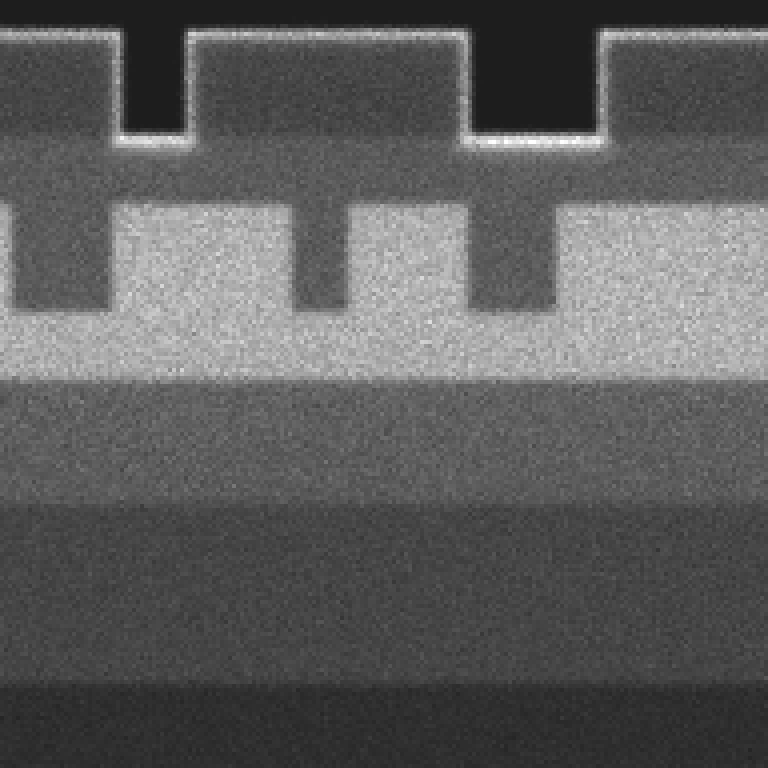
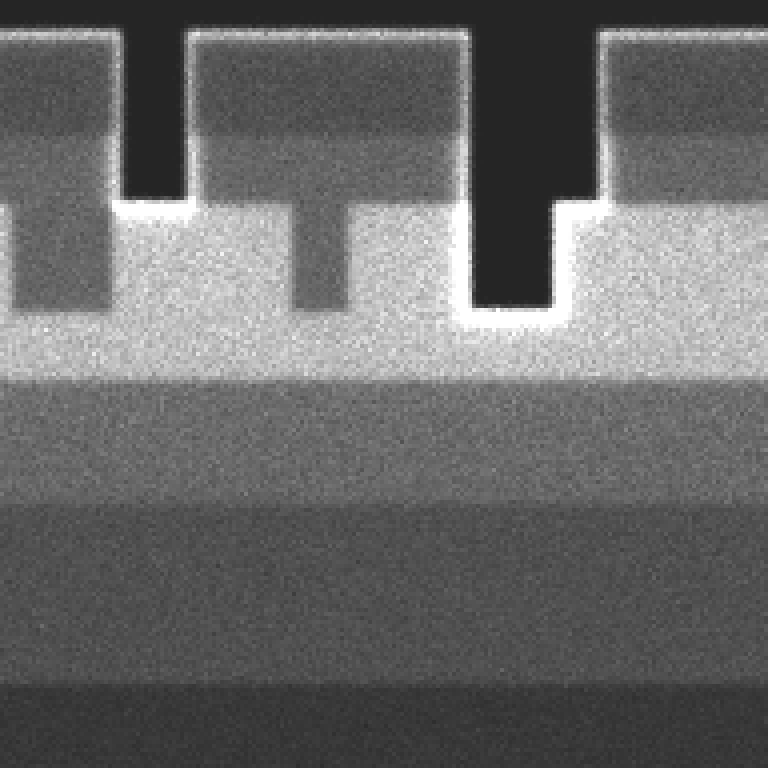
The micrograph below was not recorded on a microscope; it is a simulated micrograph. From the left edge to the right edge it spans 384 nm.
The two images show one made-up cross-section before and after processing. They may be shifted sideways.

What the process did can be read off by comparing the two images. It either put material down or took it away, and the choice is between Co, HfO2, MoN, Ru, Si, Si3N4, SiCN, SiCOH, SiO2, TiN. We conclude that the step removed SiO2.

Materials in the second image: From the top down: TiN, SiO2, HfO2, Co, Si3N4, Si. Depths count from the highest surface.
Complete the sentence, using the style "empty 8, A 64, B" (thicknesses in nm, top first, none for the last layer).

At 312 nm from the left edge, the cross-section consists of TiN 52, SiO2 34, HfO2 88, Co 62, Si3N4 90, Si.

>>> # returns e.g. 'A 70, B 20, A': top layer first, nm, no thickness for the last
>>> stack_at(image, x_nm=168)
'TiN 52, SiO2 88, HfO2 34, Co 62, Si3N4 90, Si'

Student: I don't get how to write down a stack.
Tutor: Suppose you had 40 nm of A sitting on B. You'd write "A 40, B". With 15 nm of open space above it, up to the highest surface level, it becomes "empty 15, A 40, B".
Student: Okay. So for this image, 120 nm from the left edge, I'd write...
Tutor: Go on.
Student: TiN 52, SiO2 34, HfO2 88, Co 62, Si3N4 90, Si